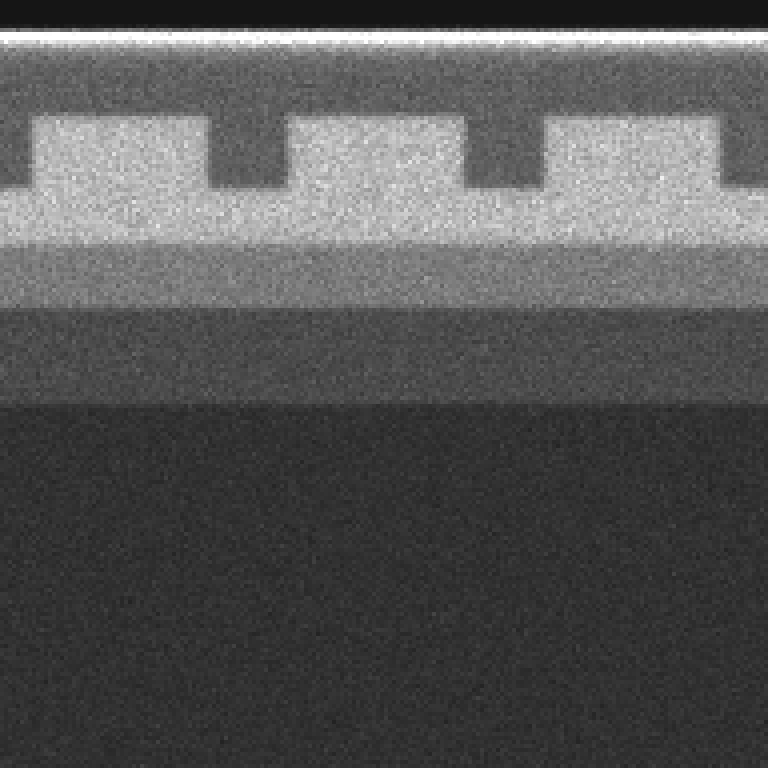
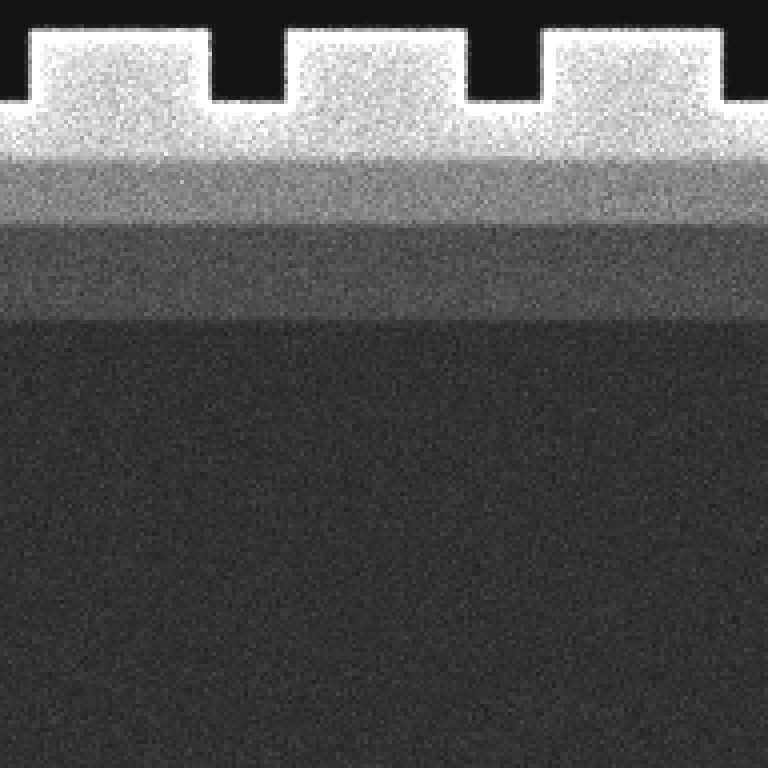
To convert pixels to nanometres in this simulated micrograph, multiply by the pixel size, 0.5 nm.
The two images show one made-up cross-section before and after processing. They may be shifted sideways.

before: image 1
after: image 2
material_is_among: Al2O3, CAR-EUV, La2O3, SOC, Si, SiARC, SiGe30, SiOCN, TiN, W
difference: SOC, removed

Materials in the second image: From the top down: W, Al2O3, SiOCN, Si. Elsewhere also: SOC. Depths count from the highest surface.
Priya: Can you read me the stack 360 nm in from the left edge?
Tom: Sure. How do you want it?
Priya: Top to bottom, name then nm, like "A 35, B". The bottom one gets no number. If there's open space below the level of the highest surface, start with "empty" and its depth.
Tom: empty 36, W 28, Al2O3 32, SiOCN 48, Si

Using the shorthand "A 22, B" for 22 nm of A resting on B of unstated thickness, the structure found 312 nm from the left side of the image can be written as W 64, Al2O3 32, SiOCN 48, Si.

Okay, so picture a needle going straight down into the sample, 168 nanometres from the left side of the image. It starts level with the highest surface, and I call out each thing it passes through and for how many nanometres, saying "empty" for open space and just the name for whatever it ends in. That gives W 64, Al2O3 32, SiOCN 48, Si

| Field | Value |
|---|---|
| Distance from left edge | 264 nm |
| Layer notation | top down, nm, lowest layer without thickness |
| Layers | empty 36, W 28, Al2O3 32, SiOCN 48, Si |